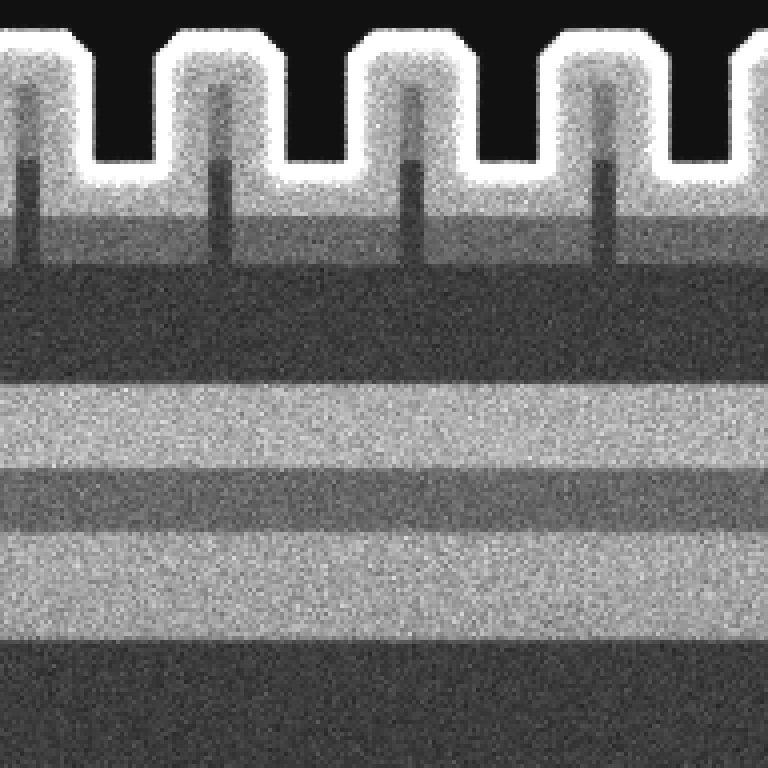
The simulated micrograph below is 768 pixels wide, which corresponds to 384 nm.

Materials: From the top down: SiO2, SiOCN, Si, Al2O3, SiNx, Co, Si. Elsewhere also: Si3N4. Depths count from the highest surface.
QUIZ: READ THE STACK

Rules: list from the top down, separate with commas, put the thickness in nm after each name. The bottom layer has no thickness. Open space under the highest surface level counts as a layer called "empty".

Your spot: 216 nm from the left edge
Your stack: SiO2 92, SiOCN 24, Si 60, Al2O3 42, SiNx 32, Co 54, Si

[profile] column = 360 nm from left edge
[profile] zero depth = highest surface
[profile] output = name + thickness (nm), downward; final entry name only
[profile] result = empty 66, SiO2 26, SiOCN 24, Si 60, Al2O3 42, SiNx 32, Co 54, Si